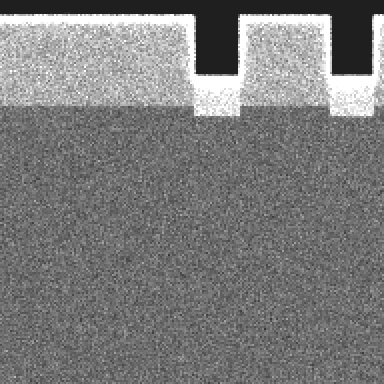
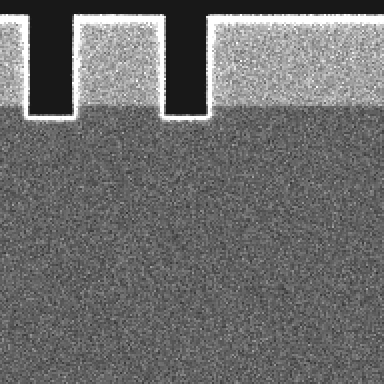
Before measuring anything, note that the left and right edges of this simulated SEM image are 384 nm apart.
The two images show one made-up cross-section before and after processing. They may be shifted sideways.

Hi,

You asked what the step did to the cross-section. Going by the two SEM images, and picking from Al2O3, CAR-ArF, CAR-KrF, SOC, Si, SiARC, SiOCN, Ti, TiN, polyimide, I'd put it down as SOC, removed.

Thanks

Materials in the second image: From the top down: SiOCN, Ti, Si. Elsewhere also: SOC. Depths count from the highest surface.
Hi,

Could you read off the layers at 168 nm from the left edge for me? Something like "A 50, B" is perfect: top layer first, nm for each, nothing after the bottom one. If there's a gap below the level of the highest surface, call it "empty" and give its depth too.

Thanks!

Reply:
empty 100, Si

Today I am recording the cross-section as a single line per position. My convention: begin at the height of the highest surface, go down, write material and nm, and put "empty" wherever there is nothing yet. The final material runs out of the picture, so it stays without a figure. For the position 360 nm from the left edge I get SiOCN 26, Ti 64, Si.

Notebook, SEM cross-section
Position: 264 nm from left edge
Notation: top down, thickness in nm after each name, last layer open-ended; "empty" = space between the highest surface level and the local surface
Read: SiOCN 26, Ti 64, Si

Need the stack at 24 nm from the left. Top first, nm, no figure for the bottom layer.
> SiOCN 26, Ti 64, Si